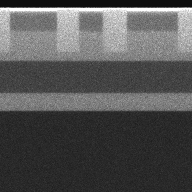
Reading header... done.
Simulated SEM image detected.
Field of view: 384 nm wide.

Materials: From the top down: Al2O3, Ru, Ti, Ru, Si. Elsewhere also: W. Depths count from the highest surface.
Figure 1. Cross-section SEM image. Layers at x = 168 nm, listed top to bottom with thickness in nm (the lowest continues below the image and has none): Al2O3 46, Ru 60, Ti 64, Ru 36, Si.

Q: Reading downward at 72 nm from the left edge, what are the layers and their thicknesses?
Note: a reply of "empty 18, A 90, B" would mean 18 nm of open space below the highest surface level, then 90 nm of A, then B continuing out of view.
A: Al2O3 46, Ru 60, Ti 64, Ru 36, Si